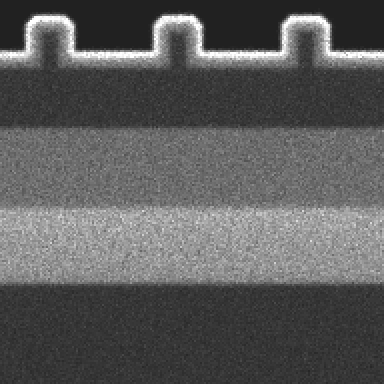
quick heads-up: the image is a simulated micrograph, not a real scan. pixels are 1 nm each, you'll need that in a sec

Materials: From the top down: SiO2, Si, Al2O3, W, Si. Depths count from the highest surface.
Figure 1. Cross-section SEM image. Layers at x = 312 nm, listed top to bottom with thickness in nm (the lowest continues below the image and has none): SiO2 16, Si 96, Al2O3 80, W 76, Si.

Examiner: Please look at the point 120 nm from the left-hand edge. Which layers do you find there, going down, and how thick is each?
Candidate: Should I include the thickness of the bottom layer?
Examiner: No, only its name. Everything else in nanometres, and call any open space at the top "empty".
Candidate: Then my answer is empty 36, SiO2 16, Si 60, Al2O3 80, W 76, Si